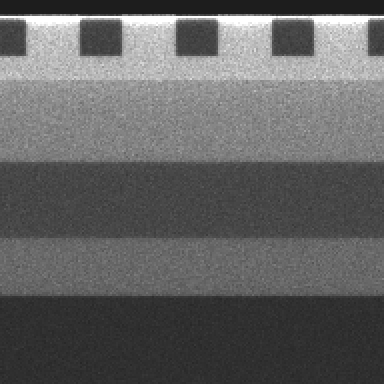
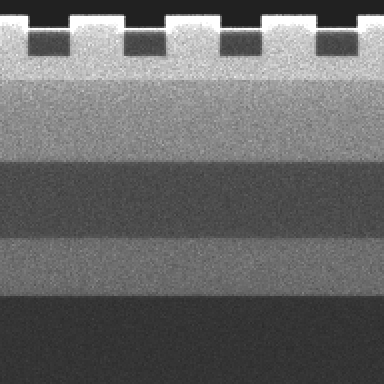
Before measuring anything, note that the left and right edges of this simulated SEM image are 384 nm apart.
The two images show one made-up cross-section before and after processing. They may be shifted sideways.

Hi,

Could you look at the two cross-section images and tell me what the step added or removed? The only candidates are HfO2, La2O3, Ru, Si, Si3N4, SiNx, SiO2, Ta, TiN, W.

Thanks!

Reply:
removed SiNx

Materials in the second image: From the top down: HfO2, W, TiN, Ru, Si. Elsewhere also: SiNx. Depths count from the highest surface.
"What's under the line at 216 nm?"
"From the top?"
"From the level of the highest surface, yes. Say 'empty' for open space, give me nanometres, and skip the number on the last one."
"HfO2 64, W 82, TiN 76, Ru 58, Si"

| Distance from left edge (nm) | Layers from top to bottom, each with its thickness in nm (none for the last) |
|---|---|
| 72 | HfO2 64, W 82, TiN 76, Ru 58, Si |